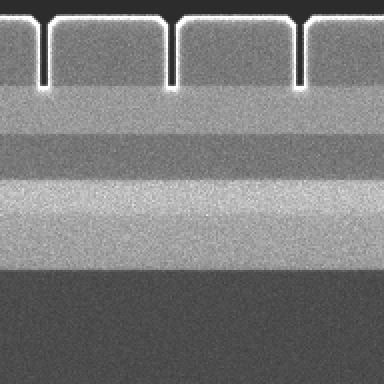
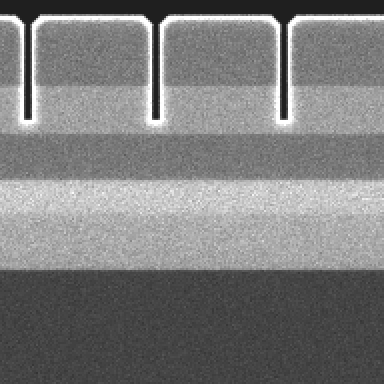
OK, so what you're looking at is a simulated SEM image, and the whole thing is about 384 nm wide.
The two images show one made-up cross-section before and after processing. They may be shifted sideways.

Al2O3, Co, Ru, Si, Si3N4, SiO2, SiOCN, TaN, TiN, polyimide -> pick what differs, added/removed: SiO2 removed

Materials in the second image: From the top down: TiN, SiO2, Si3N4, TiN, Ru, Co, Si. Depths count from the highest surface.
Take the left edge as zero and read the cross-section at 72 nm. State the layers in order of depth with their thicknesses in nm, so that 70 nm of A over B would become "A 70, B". TiN 70, SiO2 48, Si3N4 32, TiN 14, Ru 34, Co 56, Si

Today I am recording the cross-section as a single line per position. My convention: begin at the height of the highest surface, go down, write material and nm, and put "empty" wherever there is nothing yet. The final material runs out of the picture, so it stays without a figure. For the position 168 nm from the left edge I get Si3N4 70, SiO2 48, Si3N4 32, TiN 14, Ru 34, Co 56, Si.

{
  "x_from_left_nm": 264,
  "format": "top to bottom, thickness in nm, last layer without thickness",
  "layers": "Si3N4 70, SiO2 48, Si3N4 32, TiN 14, Ru 34, Co 56, Si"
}